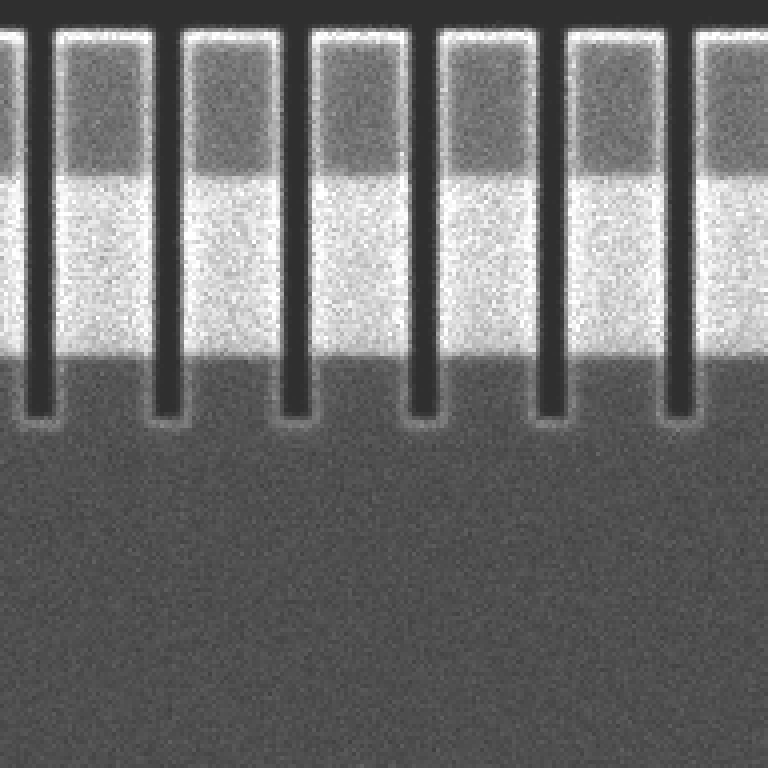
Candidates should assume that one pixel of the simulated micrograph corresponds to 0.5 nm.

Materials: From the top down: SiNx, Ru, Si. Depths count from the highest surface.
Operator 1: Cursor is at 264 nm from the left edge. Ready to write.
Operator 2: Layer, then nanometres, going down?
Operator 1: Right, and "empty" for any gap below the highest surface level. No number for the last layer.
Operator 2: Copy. SiNx 72, Ru 90, Si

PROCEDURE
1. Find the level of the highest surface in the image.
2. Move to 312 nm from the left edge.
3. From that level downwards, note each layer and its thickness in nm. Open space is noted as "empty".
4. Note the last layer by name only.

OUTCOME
SiNx 72, Ru 90, Si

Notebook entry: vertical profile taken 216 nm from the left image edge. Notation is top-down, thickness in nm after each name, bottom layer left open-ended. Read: empty 194, Si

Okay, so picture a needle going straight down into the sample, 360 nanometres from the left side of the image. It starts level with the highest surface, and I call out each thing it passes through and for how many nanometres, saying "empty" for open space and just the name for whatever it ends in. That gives SiNx 72, Ru 90, Si